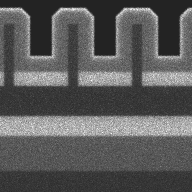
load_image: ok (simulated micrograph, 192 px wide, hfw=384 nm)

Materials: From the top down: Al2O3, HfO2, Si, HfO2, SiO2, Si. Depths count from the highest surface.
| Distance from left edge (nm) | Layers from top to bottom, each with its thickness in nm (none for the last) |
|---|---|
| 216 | empty 96, Al2O3 32, HfO2 28, Si 60, HfO2 40, SiO2 70, Si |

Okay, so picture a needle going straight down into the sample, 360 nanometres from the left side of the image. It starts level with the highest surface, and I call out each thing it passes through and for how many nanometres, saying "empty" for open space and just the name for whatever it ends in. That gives empty 16, Al2O3 112, HfO2 28, Si 60, HfO2 40, SiO2 70, Si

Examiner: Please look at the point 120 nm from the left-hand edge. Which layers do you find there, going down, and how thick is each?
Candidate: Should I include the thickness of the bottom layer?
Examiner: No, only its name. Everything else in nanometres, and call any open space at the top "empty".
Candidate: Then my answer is Al2O3 128, HfO2 28, Si 60, HfO2 40, SiO2 70, Si